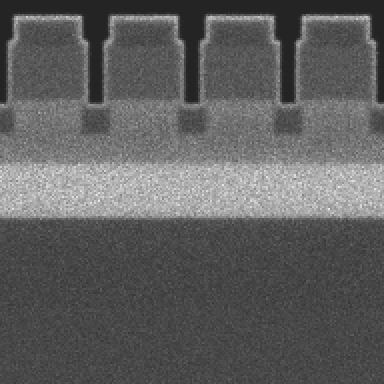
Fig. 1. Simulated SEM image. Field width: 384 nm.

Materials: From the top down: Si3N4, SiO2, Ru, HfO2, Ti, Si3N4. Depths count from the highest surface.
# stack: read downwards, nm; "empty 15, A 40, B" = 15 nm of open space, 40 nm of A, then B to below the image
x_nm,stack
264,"Si3N4 30, SiO2 54, Ru 64, HfO2 54, Ti 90, Si3N4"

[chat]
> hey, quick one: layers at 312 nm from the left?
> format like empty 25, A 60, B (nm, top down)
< Si3N4 30, SiO2 54, Ru 64, HfO2 54, Ti 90, Si3N4